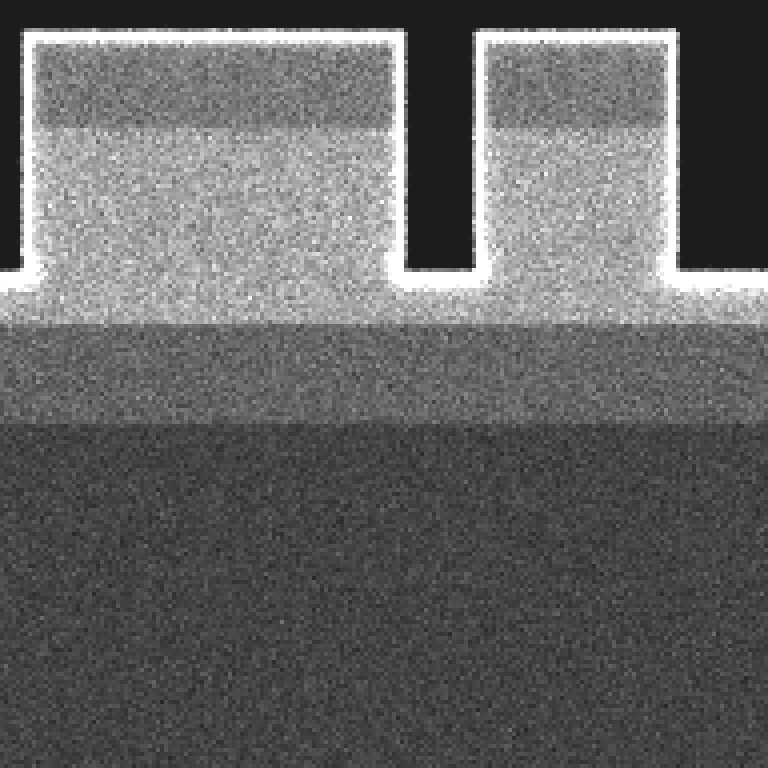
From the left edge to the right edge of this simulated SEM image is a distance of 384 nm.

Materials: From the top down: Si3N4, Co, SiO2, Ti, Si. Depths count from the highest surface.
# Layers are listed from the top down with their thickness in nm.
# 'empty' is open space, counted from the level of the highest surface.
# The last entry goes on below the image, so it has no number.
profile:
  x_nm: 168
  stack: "Si3N4 48, Co 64, SiO2 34, Ti 50, Si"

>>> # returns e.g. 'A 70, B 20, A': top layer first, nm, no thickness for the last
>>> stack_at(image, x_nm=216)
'empty 120, SiO2 26, Ti 50, Si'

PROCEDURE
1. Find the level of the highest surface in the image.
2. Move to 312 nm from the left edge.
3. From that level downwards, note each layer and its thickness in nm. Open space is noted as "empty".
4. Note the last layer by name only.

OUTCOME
Si3N4 48, Co 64, SiO2 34, Ti 50, Si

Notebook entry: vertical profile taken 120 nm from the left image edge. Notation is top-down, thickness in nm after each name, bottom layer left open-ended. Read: Si3N4 48, Co 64, SiO2 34, Ti 50, Si